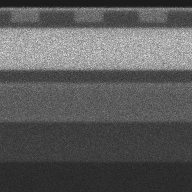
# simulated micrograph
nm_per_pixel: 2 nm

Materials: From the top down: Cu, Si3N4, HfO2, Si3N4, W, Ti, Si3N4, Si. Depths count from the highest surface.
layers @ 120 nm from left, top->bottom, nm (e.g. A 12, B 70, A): Si3N4 40, HfO2 84, Si3N4 26, W 78, Ti 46, Si3N4 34, Si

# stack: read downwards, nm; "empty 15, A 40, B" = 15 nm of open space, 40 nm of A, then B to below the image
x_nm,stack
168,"Cu 28, Si3N4 12, HfO2 84, Si3N4 26, W 78, Ti 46, Si3N4 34, Si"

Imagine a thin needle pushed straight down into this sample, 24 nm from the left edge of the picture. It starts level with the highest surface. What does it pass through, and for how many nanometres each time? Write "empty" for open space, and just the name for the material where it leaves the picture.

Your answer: Cu 28, Si3N4 12, HfO2 84, Si3N4 26, W 78, Ti 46, Si3N4 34, Si